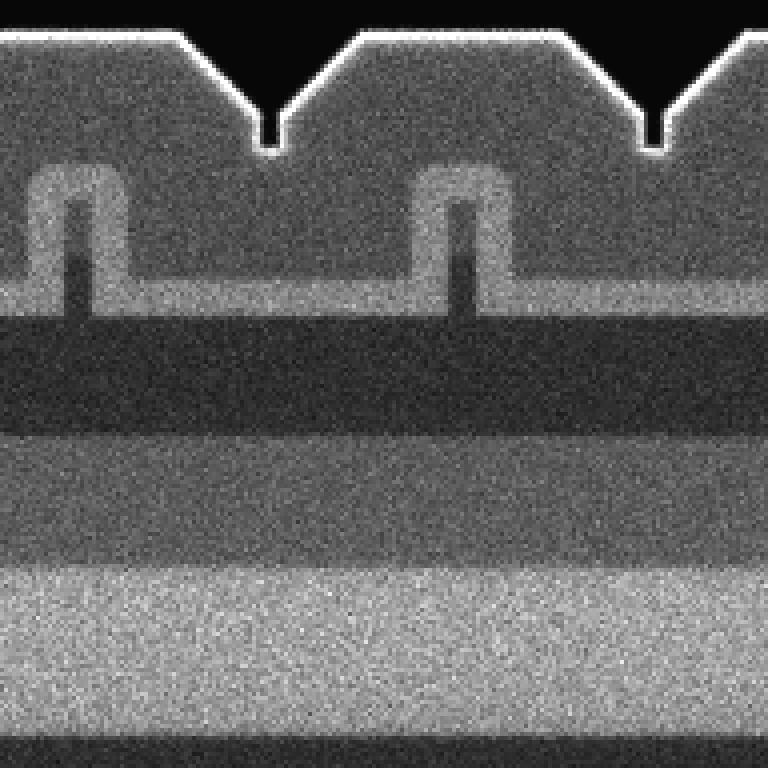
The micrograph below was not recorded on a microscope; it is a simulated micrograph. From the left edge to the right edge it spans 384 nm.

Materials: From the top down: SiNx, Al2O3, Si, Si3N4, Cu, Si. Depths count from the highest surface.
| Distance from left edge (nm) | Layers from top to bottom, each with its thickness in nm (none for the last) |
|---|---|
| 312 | empty 32, SiNx 92, Al2O3 18, Si 60, Si3N4 66, Cu 84, Si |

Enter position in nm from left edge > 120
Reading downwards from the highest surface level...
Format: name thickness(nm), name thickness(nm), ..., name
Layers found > empty 32, SiNx 92, Al2O3 18, Si 60, Si3N4 66, Cu 84, Si